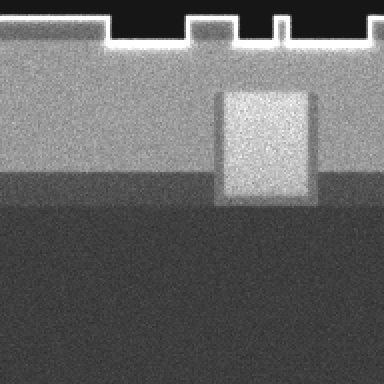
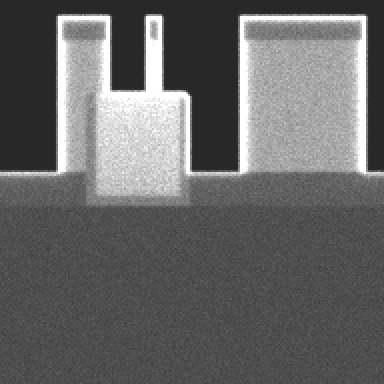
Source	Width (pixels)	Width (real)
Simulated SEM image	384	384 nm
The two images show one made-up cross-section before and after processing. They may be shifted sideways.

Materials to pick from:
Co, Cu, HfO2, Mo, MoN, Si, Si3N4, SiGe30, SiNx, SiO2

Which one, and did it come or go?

SiO2 - removed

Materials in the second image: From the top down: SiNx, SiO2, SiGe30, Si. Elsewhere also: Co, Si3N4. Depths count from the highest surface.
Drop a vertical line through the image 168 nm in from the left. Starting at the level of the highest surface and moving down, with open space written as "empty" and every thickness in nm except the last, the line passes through empty 76, Co 104, Si3N4 10, Si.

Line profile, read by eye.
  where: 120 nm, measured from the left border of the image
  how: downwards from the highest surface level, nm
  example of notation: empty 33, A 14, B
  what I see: empty 76, Co 104, Si3N4 10, Si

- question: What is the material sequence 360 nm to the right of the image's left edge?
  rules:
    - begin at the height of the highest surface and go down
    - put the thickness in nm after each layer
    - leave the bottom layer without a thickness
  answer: SiNx 24, SiO2 132, SiGe30 34, Si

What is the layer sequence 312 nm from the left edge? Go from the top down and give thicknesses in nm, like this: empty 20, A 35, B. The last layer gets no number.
SiNx 24, SiO2 132, SiGe30 34, Si